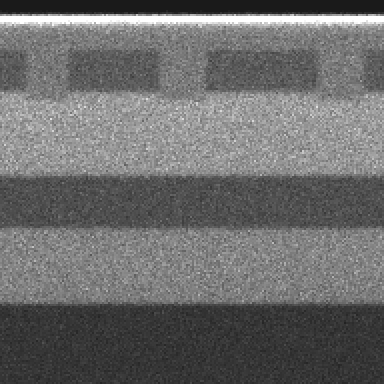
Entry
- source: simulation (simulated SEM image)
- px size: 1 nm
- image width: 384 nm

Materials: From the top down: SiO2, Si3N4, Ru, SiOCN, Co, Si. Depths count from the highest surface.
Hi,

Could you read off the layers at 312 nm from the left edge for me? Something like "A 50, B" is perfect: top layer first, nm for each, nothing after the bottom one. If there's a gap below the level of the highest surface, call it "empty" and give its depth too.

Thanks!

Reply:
SiO2 34, Si3N4 42, Ru 84, SiOCN 52, Co 76, Si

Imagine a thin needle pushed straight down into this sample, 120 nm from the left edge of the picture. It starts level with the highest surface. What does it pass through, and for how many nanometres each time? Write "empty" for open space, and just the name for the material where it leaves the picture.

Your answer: SiO2 34, Si3N4 42, Ru 84, SiOCN 52, Co 76, Si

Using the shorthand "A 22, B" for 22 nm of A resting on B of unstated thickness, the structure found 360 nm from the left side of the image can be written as SiO2 84, Ru 76, SiOCN 52, Co 76, Si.